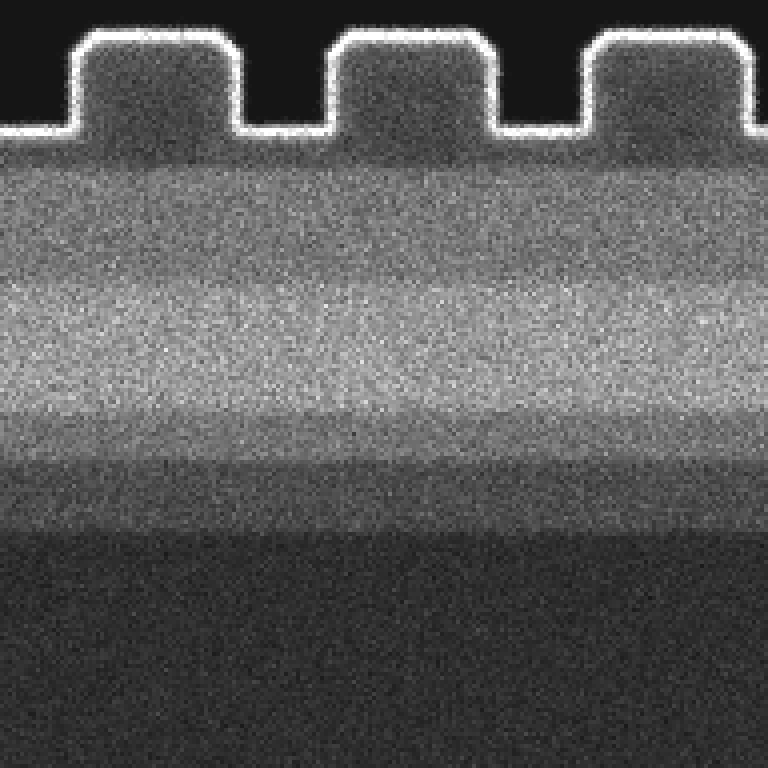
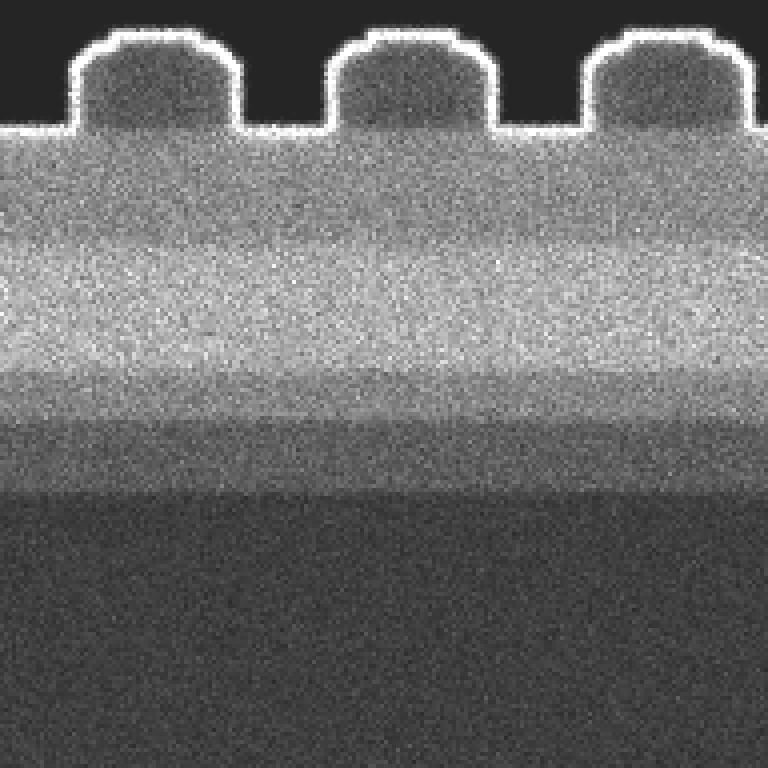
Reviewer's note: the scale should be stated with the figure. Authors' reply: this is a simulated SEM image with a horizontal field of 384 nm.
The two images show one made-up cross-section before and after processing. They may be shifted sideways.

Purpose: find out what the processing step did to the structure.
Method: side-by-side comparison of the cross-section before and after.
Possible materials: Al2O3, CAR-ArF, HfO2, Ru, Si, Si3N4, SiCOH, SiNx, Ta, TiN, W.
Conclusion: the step removed Si3N4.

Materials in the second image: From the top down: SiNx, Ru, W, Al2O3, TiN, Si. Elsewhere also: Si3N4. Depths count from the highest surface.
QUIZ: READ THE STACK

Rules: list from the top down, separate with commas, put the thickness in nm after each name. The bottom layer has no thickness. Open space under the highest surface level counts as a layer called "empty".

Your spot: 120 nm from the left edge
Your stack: empty 48, Ru 58, W 64, Al2O3 24, TiN 36, Si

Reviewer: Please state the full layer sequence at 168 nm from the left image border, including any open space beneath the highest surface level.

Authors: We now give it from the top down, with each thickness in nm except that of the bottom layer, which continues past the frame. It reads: empty 12, Si3N4 36, Ru 58, W 64, Al2O3 24, TiN 36, Si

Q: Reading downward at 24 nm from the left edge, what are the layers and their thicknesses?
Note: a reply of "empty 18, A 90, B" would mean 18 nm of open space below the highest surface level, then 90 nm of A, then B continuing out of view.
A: empty 48, Ru 58, W 64, Al2O3 24, TiN 36, Si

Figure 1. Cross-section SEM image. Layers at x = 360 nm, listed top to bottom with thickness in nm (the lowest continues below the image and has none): empty 6, Si3N4 42, Ru 58, W 64, Al2O3 24, TiN 36, Si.